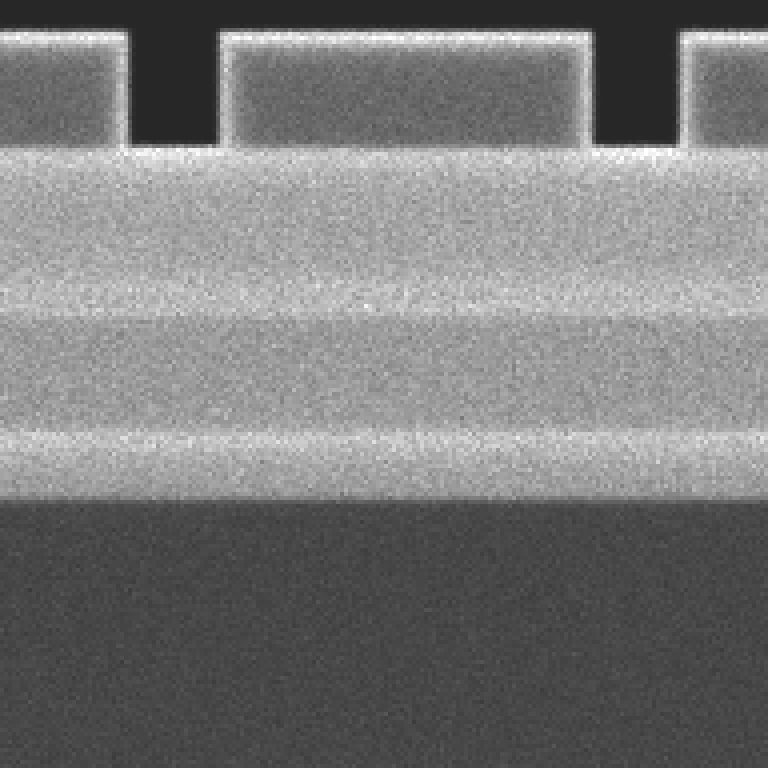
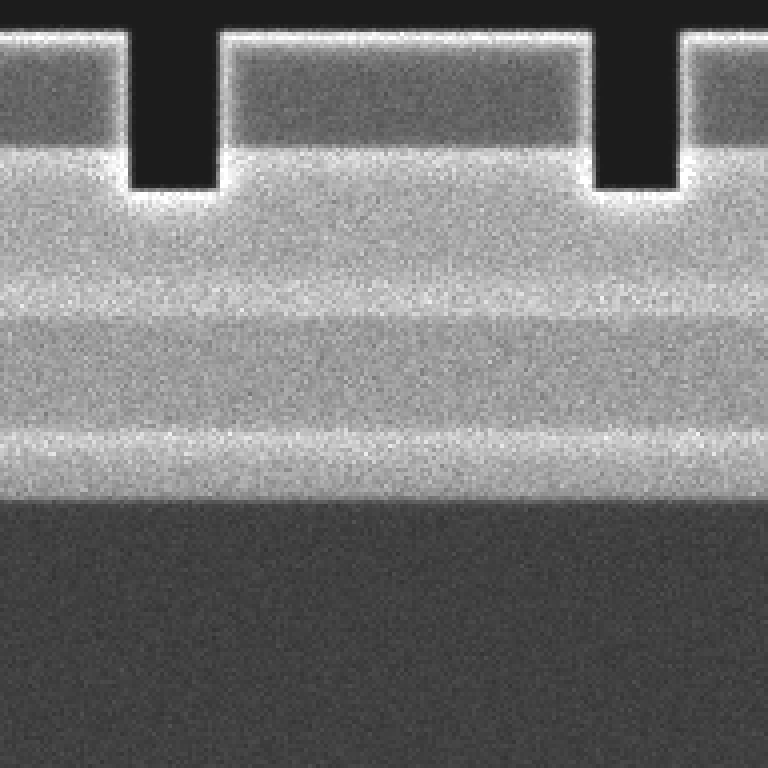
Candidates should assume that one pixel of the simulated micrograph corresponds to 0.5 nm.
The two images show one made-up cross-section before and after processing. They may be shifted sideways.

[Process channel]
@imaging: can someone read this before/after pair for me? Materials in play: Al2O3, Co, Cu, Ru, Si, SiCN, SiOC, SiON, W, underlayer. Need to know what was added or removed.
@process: W removed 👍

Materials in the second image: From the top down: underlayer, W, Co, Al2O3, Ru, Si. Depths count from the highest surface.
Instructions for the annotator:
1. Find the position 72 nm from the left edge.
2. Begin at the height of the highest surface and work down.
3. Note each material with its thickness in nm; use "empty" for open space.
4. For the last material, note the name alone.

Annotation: empty 80, W 50, Co 12, Al2O3 58, Ru 34, Si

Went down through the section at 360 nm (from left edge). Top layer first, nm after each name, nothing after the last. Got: underlayer 58, W 72, Co 12, Al2O3 58, Ru 34, Si